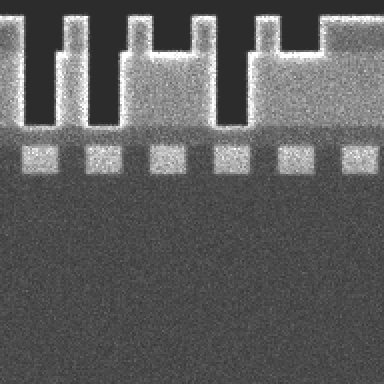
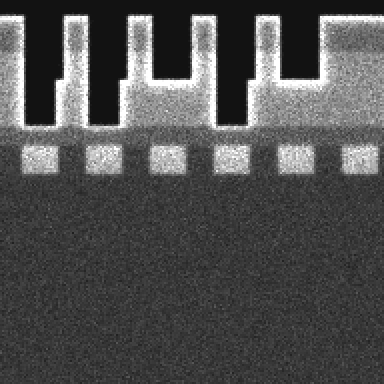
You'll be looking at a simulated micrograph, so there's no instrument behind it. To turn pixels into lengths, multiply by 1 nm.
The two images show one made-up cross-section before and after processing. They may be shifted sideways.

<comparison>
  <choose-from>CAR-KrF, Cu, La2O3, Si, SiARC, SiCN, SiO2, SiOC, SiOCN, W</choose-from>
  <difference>SiO2 removed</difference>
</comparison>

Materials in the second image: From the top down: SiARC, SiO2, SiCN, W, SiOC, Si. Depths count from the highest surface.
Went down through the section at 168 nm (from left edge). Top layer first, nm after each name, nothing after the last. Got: empty 64, SiO2 46, SiCN 20, W 28, SiOC 38, Si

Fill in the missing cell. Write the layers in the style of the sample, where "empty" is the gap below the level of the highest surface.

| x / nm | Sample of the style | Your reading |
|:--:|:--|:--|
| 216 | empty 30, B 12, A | empty 110, SiCN 20, W 28, SiOC 38, Si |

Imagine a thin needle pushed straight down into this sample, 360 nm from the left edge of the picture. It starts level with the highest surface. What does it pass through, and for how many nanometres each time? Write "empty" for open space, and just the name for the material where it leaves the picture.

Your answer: SiARC 36, SiO2 74, SiCN 20, W 28, SiOC 38, Si